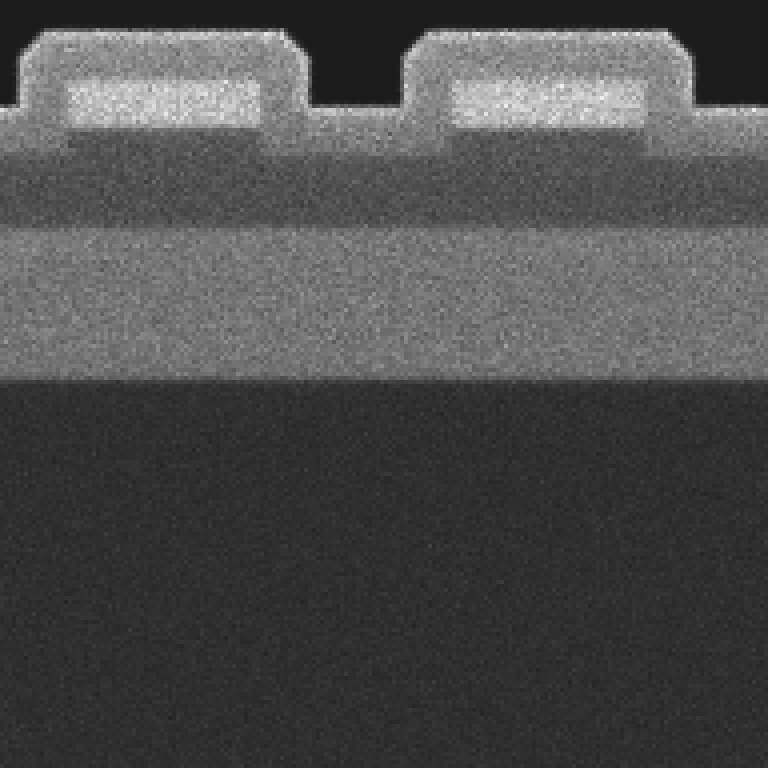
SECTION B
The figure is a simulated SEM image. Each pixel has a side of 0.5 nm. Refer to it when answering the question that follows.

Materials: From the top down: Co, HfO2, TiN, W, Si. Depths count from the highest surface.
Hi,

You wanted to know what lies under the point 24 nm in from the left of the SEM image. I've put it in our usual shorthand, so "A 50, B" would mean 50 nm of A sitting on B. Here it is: Co 62, TiN 36, W 76, Si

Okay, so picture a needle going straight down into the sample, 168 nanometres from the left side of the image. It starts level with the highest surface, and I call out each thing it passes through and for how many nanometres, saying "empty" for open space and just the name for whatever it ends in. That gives empty 38, Co 24, TiN 36, W 76, Si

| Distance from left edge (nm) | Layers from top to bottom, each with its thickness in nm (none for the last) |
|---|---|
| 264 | Co 24, HfO2 24, TiN 50, W 76, Si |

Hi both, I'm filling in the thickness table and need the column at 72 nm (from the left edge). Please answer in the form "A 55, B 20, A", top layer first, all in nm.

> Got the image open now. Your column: Co 24, HfO2 24, TiN 50, W 76, Si